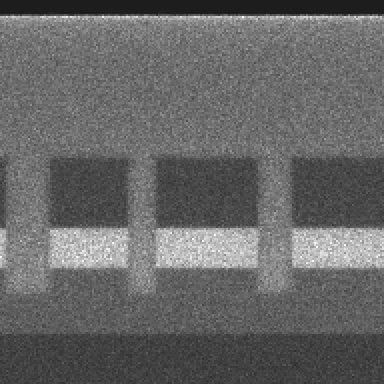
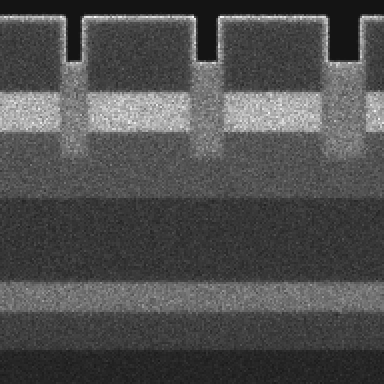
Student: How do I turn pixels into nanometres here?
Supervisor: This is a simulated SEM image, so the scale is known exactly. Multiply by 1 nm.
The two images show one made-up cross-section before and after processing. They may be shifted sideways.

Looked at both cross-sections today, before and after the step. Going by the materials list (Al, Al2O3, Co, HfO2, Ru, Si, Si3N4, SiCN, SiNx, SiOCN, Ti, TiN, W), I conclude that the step removed Ru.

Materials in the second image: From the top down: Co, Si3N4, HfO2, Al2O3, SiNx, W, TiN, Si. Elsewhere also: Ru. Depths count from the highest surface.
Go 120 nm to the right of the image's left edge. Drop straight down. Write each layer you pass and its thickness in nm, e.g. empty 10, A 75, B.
Co 6, Si3N4 70, HfO2 40, Al2O3 66, SiNx 84, W 30, TiN 38, Si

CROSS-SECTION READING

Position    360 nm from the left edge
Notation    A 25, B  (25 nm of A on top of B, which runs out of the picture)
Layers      empty 2, Co 140, Al2O3 40, SiNx 84, W 30, TiN 38, Si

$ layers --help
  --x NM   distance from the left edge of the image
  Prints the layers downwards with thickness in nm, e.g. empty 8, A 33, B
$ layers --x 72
empty 46, Ru 90, Co 6, Al2O3 40, SiNx 84, W 30, TiN 38, Si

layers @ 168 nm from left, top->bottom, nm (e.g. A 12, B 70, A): Co 6, Si3N4 70, HfO2 40, Al2O3 66, SiNx 84, W 30, TiN 38, Si